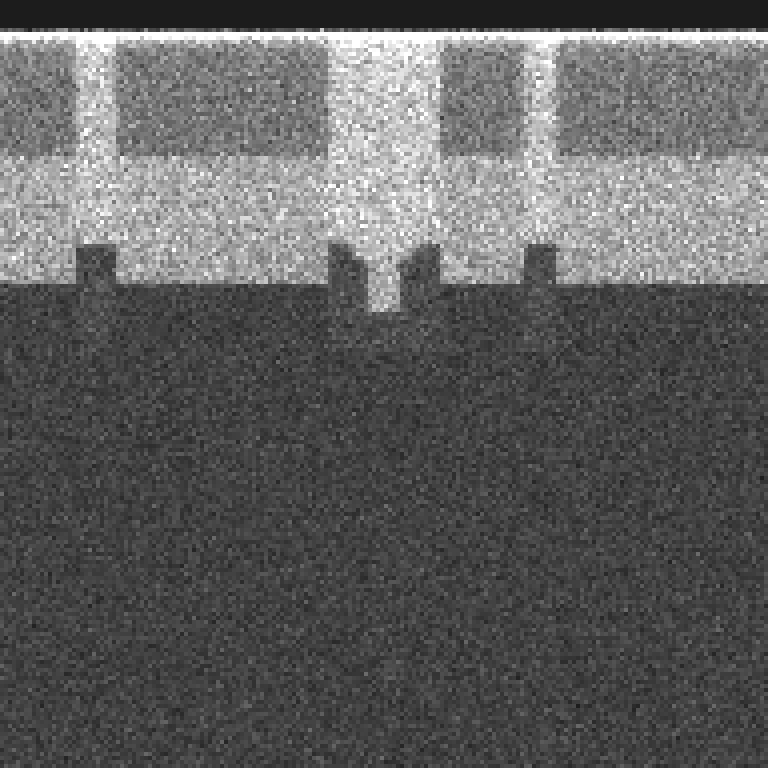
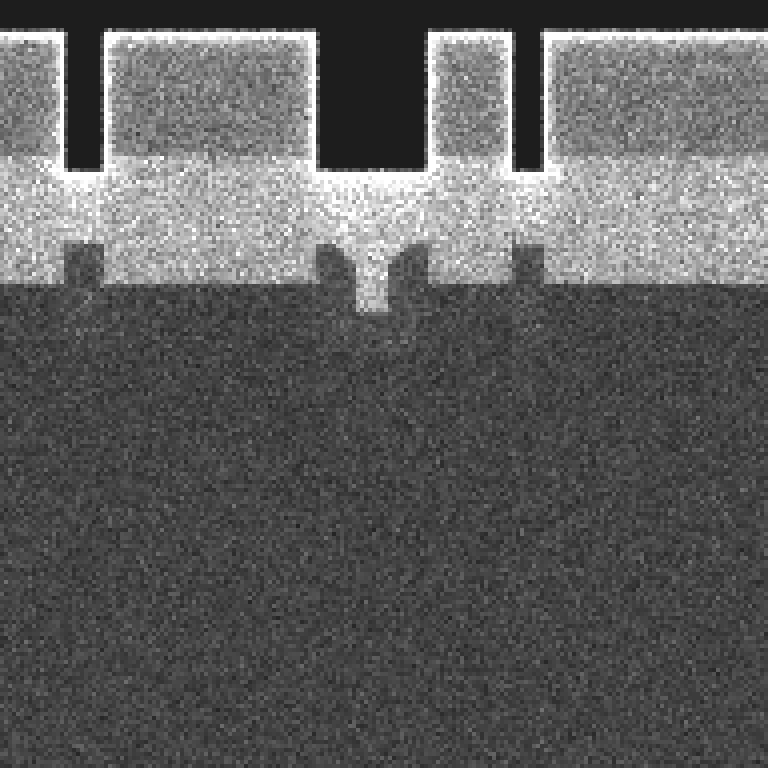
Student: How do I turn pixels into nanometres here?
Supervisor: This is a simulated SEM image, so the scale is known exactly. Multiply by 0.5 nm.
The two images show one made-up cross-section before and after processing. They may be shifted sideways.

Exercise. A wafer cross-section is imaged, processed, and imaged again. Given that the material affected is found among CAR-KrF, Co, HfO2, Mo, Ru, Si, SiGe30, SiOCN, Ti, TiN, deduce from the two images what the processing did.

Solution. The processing removed Ru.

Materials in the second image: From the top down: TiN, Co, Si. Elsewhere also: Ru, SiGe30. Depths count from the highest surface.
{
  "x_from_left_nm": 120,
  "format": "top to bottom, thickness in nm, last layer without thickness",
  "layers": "TiN 62, Co 64, Si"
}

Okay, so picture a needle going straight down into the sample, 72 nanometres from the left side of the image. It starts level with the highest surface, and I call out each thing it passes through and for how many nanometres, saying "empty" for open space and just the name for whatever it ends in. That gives TiN 62, Co 64, Si